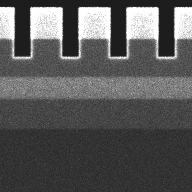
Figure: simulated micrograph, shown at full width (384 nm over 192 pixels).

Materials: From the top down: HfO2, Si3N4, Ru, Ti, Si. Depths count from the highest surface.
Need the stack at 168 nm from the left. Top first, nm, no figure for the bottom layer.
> HfO2 62, Si3N4 76, Ru 44, Ti 60, Si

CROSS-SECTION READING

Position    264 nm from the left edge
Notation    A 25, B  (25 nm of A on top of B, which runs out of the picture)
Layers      HfO2 62, Si3N4 76, Ru 44, Ti 60, Si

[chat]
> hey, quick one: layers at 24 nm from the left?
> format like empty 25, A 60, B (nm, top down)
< HfO2 62, Si3N4 76, Ru 44, Ti 60, Si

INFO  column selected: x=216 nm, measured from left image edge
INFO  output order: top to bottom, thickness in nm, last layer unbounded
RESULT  HfO2 62, Si3N4 76, Ru 44, Ti 60, Si